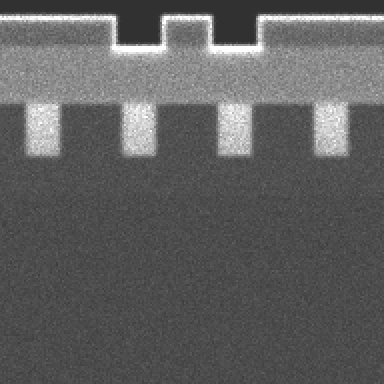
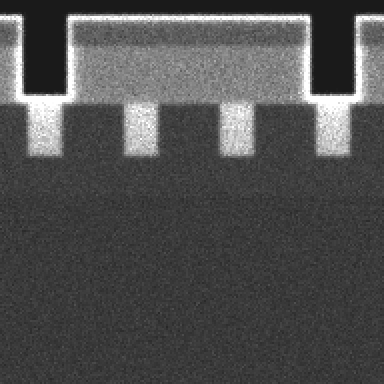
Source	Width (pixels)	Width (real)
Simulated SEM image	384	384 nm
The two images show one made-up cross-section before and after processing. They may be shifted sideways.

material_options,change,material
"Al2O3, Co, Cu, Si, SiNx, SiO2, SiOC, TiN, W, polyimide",removed,SiO2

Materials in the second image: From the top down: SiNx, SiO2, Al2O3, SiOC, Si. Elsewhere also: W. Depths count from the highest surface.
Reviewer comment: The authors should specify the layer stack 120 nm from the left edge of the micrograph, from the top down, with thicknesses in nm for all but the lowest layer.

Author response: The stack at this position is SiNx 30, SiO2 50, Al2O3 8, SiOC 92, Si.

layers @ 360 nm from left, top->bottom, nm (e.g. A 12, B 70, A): SiNx 30, SiO2 50, Al2O3 8, SiOC 92, Si